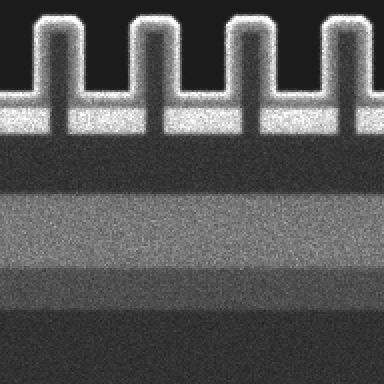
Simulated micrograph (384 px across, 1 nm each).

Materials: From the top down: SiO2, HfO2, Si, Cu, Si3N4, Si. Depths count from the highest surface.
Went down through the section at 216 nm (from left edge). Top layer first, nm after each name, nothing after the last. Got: empty 76, SiO2 16, HfO2 26, Si 60, Cu 74, Si3N4 42, Si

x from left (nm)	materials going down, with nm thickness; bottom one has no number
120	empty 76, SiO2 16, HfO2 26, Si 60, Cu 74, Si3N4 42, Si